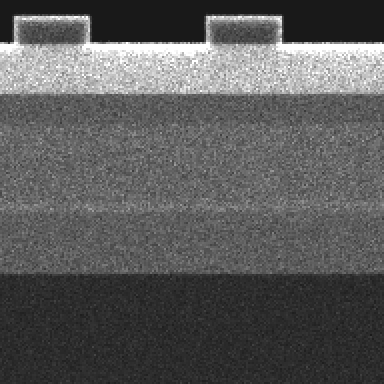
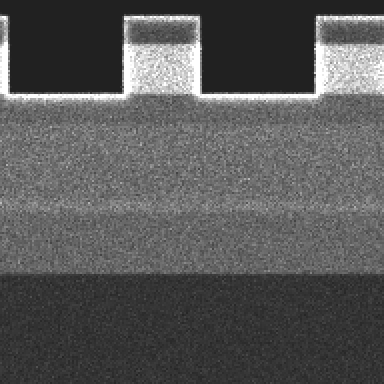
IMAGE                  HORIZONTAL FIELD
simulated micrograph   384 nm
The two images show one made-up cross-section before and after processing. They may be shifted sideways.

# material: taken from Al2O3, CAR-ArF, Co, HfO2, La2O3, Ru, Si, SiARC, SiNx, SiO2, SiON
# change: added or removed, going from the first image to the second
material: HfO2
change: removed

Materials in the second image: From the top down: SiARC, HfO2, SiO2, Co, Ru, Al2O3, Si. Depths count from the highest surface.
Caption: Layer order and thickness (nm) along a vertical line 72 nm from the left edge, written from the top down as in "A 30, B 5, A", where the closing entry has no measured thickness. empty 78, SiO2 30, Co 78, Ru 10, Al2O3 62, Si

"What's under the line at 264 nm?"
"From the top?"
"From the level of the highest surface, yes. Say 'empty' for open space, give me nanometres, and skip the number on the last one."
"empty 78, SiO2 30, Co 78, Ru 10, Al2O3 62, Si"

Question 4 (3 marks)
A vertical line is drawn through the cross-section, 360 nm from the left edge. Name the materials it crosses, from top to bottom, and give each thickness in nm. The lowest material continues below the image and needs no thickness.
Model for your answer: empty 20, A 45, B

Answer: SiARC 28, HfO2 50, SiO2 30, Co 78, Ru 10, Al2O3 62, Si